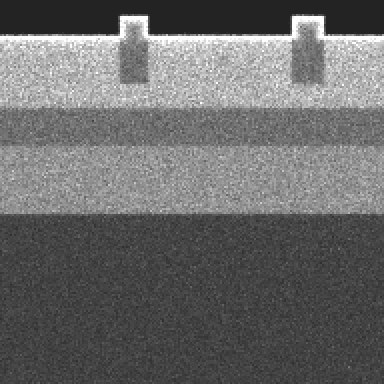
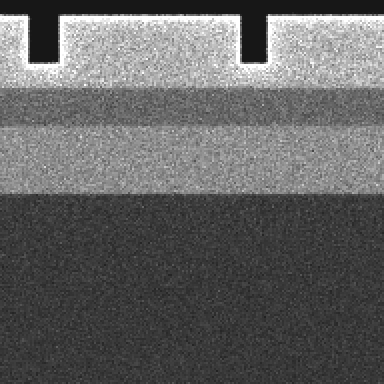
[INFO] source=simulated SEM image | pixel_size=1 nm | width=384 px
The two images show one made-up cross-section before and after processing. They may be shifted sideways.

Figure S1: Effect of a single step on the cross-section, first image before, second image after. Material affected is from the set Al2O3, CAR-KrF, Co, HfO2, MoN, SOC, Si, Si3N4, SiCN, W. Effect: removed SOC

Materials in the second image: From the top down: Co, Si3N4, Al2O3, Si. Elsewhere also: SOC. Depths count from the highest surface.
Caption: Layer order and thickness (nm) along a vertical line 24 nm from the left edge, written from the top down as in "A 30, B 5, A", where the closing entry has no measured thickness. Co 72, Si3N4 38, Al2O3 68, Si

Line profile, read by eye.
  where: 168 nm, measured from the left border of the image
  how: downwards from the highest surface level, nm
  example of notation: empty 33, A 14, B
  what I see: Co 72, Si3N4 38, Al2O3 68, Si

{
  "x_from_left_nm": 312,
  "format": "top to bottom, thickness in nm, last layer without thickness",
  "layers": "Co 72, Si3N4 38, Al2O3 68, Si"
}